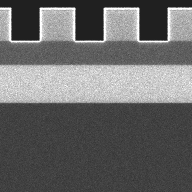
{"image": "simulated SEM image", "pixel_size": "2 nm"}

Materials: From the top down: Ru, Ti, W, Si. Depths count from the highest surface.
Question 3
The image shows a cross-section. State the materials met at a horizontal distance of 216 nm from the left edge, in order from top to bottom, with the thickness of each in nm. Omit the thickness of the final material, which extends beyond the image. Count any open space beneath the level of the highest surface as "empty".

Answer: Ru 66, Ti 48, W 76, Si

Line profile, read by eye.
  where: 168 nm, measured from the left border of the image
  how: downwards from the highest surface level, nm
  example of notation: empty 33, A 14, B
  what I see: empty 66, Ti 48, W 76, Si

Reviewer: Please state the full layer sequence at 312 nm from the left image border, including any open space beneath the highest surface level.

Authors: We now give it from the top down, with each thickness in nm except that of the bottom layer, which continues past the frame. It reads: empty 66, Ti 48, W 76, Si